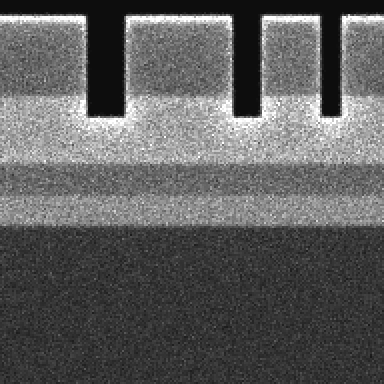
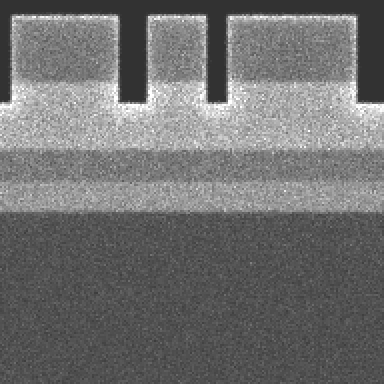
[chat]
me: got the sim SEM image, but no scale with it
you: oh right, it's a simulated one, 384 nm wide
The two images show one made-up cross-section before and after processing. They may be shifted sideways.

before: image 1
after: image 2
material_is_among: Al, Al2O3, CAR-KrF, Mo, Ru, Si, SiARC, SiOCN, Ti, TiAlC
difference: SiARC, removed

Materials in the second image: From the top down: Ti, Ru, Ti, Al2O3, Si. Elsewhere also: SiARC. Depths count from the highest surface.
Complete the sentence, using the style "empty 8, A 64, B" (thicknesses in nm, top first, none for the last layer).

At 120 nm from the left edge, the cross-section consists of empty 88, Ru 46, Ti 32, Al2O3 30, Si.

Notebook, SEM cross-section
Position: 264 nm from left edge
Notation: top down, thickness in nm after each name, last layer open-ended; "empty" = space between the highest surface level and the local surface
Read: Ti 66, Ru 68, Ti 32, Al2O3 30, Si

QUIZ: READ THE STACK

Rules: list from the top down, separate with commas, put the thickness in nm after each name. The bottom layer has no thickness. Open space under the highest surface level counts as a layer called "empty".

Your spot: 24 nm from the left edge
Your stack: Ti 66, Ru 68, Ti 32, Al2O3 30, Si